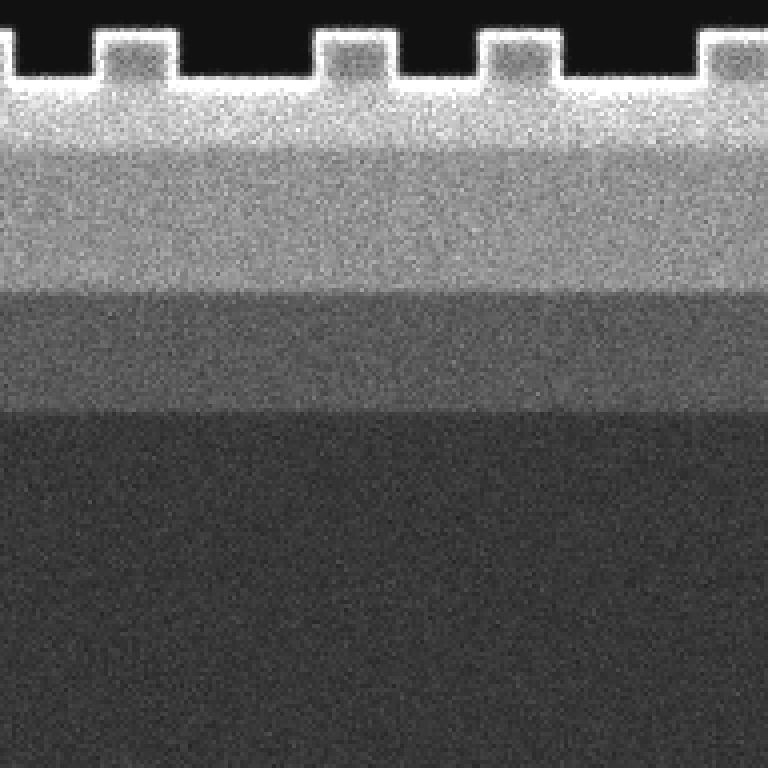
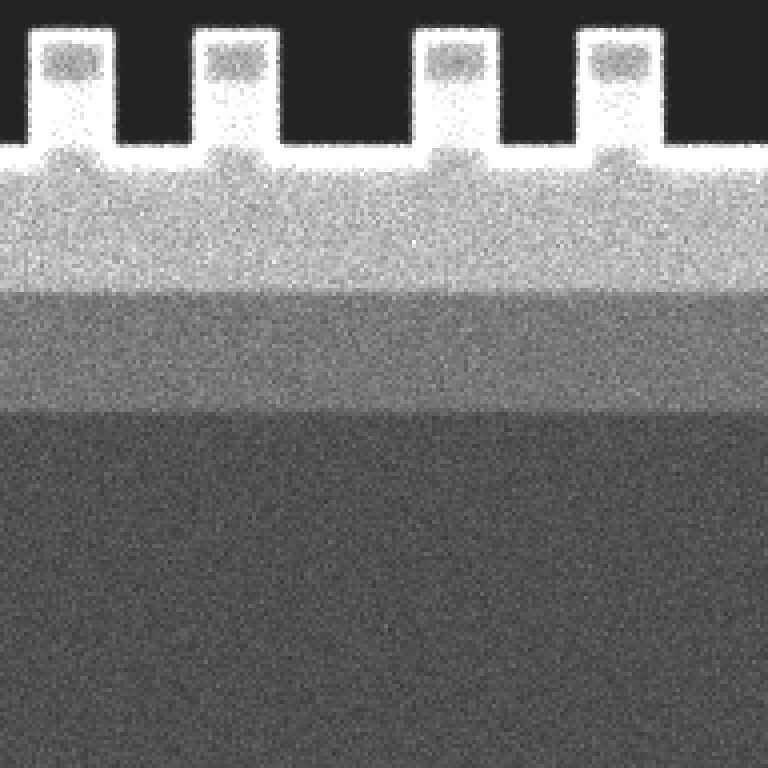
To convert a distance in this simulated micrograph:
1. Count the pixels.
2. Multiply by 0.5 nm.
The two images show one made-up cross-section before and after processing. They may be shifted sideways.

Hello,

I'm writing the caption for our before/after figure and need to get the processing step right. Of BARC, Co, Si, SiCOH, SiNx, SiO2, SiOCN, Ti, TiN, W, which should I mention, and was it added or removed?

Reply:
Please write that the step removed Co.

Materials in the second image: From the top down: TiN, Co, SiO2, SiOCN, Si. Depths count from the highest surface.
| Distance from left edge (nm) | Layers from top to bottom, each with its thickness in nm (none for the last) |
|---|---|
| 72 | empty 58, SiO2 72, SiOCN 60, Si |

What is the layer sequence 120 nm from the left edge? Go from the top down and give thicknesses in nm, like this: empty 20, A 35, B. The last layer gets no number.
TiN 24, Co 34, SiO2 72, SiOCN 60, Si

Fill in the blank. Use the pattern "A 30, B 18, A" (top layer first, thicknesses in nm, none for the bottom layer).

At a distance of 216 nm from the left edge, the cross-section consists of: TiN 24, Co 34, SiO2 72, SiOCN 60, Si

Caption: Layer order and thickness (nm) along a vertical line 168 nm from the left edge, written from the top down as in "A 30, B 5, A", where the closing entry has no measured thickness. empty 58, SiO2 72, SiOCN 60, Si